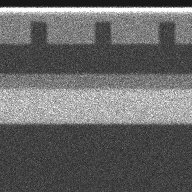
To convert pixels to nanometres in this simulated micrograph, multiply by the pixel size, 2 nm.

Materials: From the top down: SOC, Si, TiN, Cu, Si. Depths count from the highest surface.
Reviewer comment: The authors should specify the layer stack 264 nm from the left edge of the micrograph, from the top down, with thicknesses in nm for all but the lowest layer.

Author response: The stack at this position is SOC 72, Si 60, TiN 30, Cu 70, Si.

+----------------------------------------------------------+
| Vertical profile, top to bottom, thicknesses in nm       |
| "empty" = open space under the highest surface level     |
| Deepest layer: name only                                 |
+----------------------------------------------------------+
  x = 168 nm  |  SOC 72, Si 60, TiN 30, Cu 70, Si